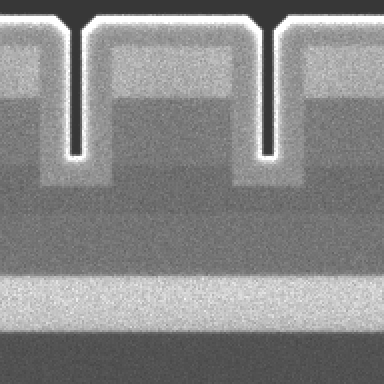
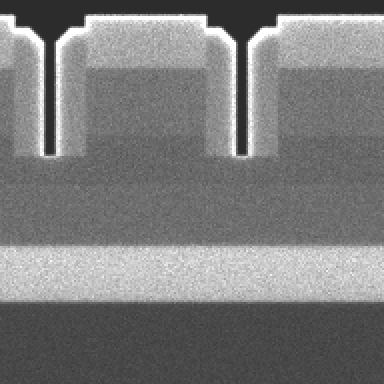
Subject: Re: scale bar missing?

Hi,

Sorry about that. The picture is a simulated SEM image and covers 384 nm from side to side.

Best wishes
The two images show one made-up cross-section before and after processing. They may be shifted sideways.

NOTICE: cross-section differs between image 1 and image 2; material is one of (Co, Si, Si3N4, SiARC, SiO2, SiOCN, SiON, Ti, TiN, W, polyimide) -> removed: SiO2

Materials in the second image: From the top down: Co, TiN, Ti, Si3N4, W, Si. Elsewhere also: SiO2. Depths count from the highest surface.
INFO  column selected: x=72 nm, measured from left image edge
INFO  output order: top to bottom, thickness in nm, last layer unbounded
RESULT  empty 12, SiO2 128, Ti 28, Si3N4 62, W 56, Si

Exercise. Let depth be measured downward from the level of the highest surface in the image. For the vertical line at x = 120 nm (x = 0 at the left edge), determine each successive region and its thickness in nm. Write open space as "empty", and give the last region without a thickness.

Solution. Co 52, TiN 68, Ti 48, Si3N4 62, W 56, Si